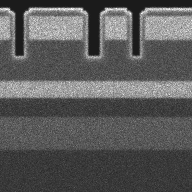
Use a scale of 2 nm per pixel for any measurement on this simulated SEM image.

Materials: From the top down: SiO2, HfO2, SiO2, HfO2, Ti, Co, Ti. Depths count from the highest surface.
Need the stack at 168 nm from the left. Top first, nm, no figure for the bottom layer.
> empty 6, SiO2 140, HfO2 34, Ti 38, Co 66, Ti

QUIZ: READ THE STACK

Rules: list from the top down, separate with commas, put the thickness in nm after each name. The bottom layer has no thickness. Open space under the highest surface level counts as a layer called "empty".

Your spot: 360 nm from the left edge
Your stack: SiO2 16, HfO2 48, SiO2 82, HfO2 34, Ti 38, Co 66, Ti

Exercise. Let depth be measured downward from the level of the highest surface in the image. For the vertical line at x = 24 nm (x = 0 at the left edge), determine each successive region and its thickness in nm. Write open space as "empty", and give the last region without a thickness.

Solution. empty 6, SiO2 140, HfO2 34, Ti 38, Co 66, Ti